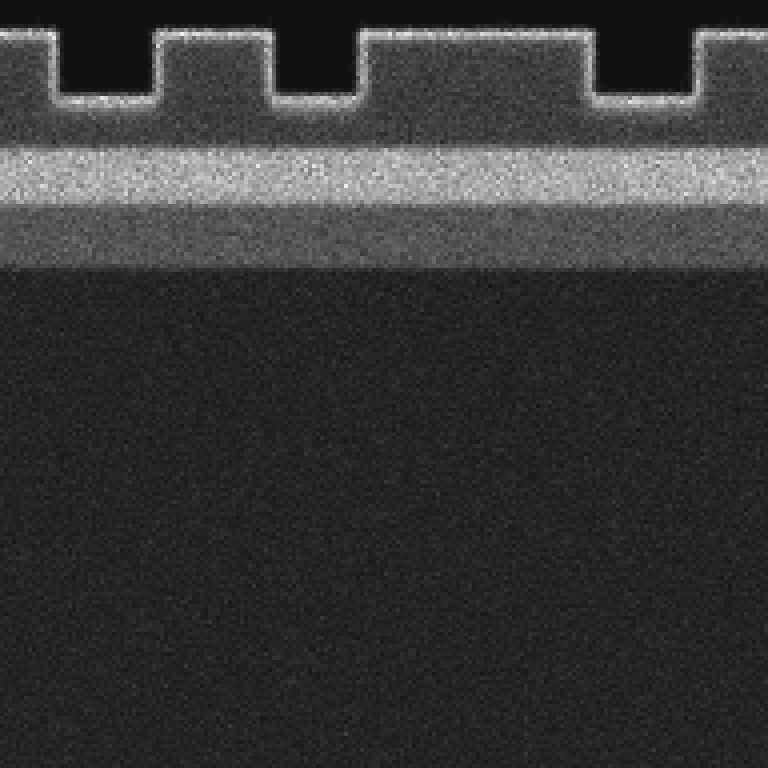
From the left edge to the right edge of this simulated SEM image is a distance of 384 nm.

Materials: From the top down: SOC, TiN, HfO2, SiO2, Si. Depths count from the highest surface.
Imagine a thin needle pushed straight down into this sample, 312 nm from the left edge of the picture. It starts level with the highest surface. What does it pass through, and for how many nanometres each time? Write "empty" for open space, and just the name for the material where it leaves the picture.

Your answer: empty 32, SOC 8, TiN 18, HfO2 28, SiO2 32, Si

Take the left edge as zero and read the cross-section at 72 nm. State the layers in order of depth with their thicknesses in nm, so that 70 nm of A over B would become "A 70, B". empty 32, SOC 8, TiN 18, HfO2 28, SiO2 32, Si